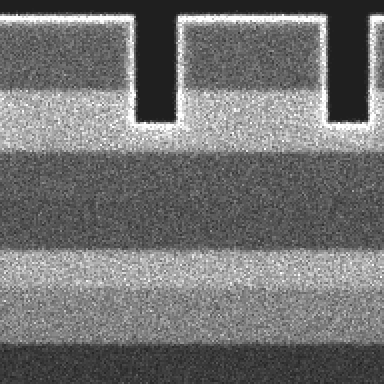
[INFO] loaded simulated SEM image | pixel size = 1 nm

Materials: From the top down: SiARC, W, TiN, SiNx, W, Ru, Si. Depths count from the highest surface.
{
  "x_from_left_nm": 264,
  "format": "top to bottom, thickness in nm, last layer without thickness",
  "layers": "SiARC 74, W 62, TiN 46, SiNx 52, W 38, Ru 56, Si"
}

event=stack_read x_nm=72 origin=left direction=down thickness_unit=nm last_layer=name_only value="SiARC 74, W 62, TiN 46, SiNx 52, W 38, Ru 56, Si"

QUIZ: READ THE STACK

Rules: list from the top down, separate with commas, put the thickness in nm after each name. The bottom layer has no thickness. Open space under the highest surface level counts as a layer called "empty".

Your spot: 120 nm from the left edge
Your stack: SiARC 74, W 62, TiN 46, SiNx 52, W 38, Ru 56, Si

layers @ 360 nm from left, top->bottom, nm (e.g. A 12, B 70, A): empty 108, W 28, TiN 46, SiNx 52, W 38, Ru 56, Si